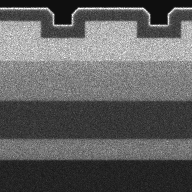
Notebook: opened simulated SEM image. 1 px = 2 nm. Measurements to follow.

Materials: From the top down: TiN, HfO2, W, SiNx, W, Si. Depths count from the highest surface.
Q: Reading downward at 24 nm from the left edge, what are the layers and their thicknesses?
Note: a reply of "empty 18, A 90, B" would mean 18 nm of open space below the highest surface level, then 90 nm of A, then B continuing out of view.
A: TiN 26, HfO2 80, W 80, SiNx 76, W 42, Si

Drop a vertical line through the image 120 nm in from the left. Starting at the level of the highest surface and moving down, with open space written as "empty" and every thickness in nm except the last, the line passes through empty 34, TiN 26, HfO2 46, W 80, SiNx 76, W 42, Si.